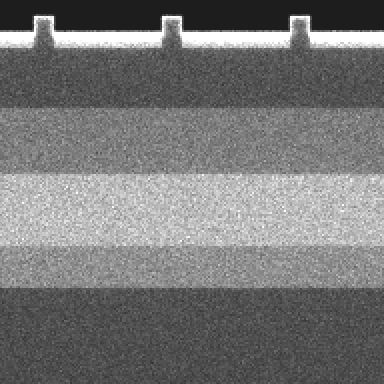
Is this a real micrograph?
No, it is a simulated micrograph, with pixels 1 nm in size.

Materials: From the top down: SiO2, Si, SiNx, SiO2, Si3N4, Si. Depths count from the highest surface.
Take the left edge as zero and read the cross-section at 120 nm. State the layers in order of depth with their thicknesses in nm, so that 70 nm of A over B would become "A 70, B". empty 16, SiO2 16, Si 60, SiNx 66, SiO2 72, Si3N4 42, Si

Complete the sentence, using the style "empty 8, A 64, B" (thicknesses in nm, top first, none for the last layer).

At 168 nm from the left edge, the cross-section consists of Si 92, SiNx 66, SiO2 72, Si3N4 42, Si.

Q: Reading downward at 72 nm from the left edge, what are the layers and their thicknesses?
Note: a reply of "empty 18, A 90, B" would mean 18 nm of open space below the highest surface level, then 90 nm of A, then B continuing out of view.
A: empty 16, SiO2 16, Si 60, SiNx 66, SiO2 72, Si3N4 42, Si